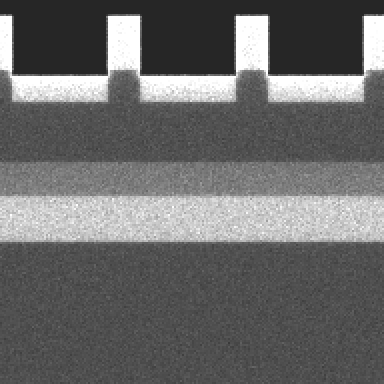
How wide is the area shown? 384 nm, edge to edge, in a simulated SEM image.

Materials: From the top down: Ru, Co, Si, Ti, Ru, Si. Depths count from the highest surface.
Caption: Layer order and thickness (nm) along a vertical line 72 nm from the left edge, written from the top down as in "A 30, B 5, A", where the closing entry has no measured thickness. empty 60, Ru 26, Si 60, Ti 34, Ru 46, Si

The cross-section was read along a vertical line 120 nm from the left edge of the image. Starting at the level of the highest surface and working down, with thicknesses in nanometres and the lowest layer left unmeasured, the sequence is Ru 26, Co 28, Si 92, Ti 34, Ru 46, Si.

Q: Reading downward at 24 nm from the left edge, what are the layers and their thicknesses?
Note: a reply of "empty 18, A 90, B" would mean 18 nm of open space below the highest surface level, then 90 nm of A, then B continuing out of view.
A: empty 60, Ru 26, Si 60, Ti 34, Ru 46, Si